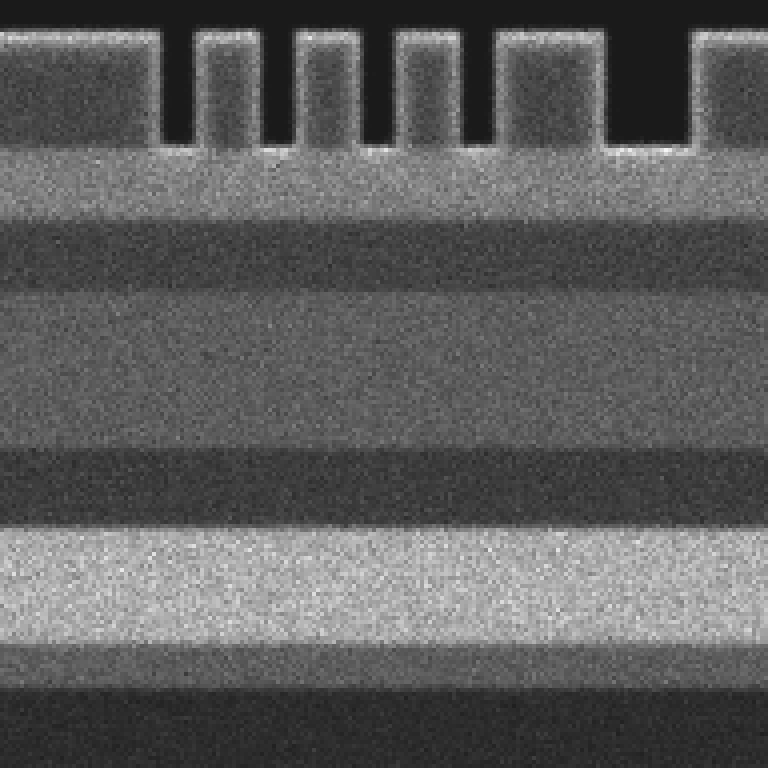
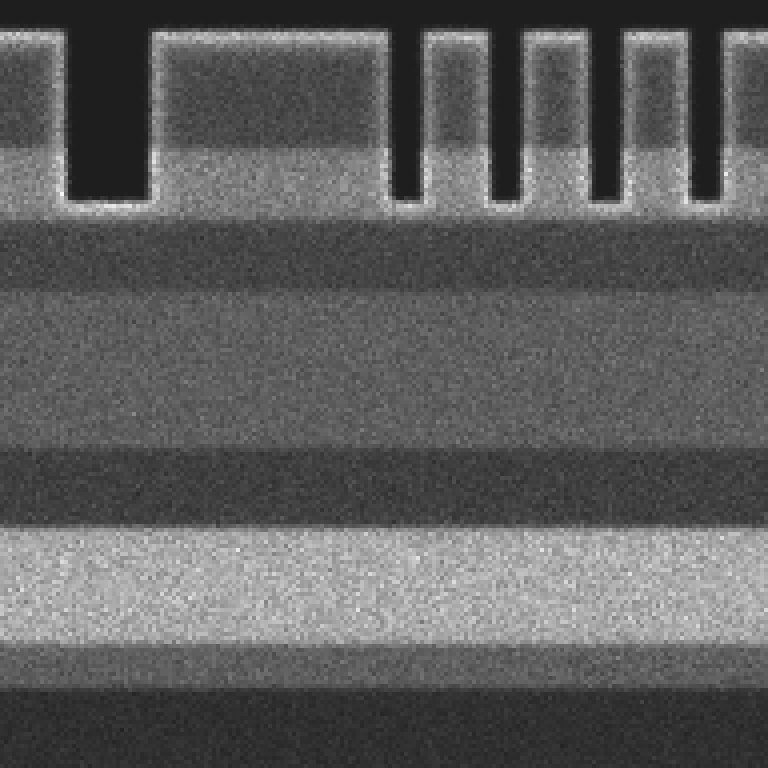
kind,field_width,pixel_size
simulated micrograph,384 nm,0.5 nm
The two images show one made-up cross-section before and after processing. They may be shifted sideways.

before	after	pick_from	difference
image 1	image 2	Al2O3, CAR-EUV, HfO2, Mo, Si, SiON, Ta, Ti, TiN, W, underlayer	W removed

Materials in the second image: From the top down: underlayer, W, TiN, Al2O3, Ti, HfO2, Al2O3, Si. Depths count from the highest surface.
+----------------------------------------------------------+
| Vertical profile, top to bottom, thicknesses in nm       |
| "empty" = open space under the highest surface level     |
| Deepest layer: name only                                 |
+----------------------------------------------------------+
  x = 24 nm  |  underlayer 58, W 36, TiN 36, Al2O3 78, Ti 40, HfO2 58, Al2O3 22, Si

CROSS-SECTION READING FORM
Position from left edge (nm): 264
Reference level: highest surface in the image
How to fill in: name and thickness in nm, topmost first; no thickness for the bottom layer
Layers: underlayer 58, W 36, TiN 36, Al2O3 78, Ti 40, HfO2 58, Al2O3 22, Si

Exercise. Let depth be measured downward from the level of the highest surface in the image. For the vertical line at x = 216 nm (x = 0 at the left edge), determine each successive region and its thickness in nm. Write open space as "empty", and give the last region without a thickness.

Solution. underlayer 58, W 36, TiN 36, Al2O3 78, Ti 40, HfO2 58, Al2O3 22, Si